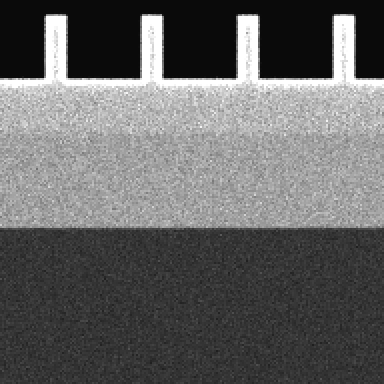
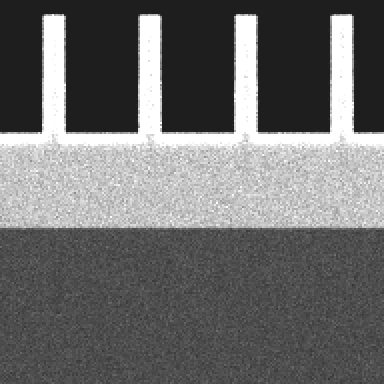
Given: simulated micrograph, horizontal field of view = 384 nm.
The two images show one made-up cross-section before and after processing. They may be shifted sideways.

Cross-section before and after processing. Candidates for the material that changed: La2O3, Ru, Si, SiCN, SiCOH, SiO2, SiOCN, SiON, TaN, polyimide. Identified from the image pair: Ru (removed).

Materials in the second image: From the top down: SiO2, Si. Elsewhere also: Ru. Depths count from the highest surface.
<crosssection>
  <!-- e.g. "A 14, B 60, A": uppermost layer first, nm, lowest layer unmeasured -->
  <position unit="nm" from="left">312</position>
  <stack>empty 118, SiO2 94, Si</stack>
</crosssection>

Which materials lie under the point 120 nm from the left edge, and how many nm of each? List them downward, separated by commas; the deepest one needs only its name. empty 118, SiO2 94, Si